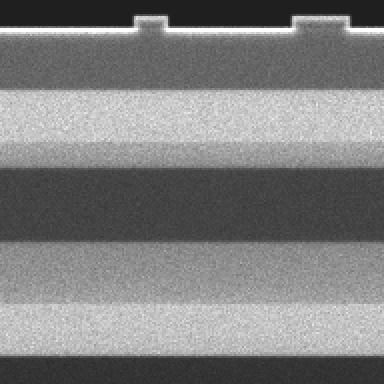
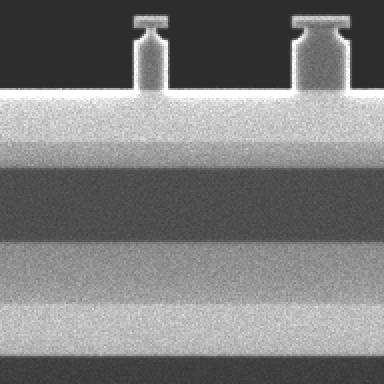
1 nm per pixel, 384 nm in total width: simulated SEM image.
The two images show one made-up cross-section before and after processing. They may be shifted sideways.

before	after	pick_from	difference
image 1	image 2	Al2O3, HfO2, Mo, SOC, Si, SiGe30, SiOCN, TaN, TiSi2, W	Al2O3 removed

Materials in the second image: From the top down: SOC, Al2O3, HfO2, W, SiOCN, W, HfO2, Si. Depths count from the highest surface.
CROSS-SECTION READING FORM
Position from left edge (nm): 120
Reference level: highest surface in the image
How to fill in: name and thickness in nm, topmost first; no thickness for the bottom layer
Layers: empty 74, HfO2 52, W 26, SiOCN 74, W 62, HfO2 52, Si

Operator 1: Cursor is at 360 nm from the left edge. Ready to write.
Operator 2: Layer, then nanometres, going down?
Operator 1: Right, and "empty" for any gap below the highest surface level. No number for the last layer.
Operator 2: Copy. empty 74, HfO2 52, W 26, SiOCN 74, W 62, HfO2 52, Si